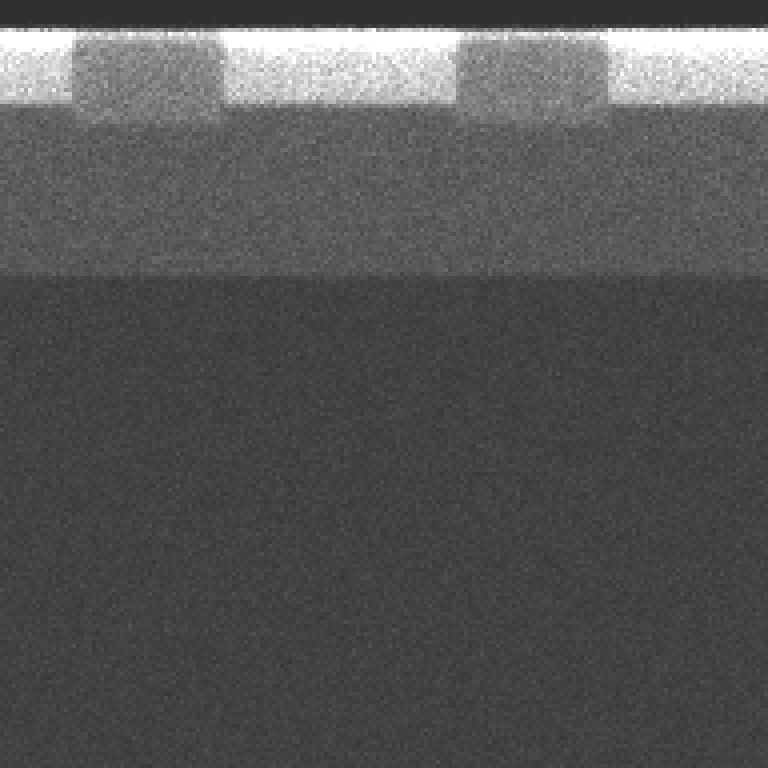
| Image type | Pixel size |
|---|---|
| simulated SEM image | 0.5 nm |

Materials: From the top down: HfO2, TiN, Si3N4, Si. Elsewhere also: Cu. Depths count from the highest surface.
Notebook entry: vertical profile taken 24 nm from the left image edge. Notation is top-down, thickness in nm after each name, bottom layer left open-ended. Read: HfO2 36, TiN 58, Si3N4 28, Si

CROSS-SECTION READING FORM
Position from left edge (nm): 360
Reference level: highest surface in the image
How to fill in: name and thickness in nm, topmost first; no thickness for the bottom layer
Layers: HfO2 36, TiN 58, Si3N4 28, Si